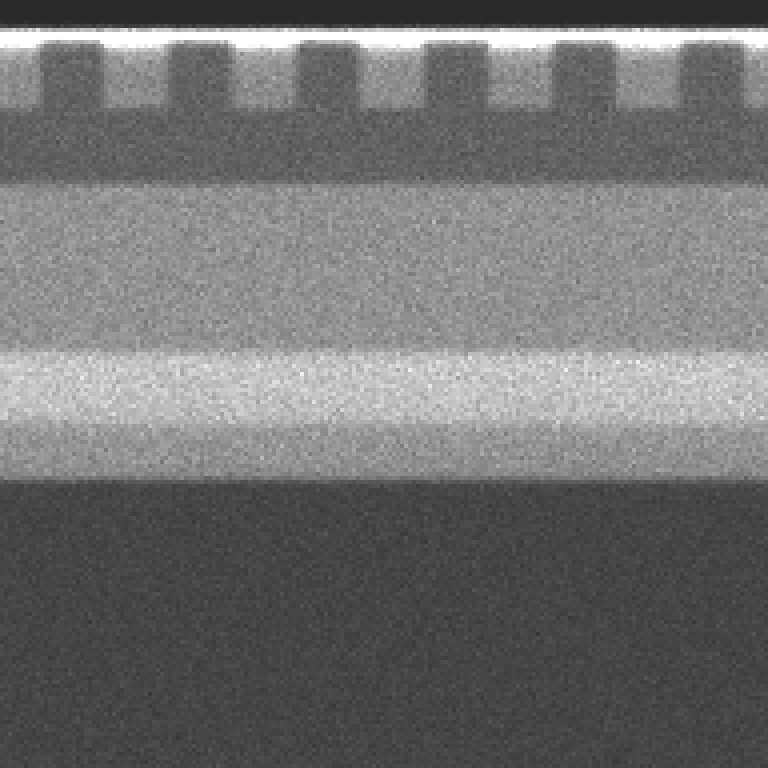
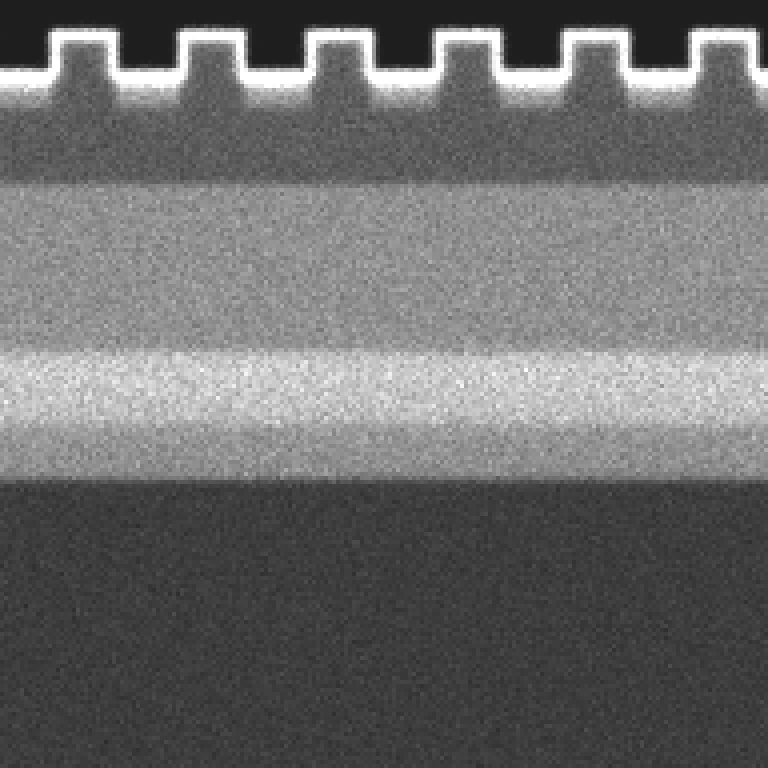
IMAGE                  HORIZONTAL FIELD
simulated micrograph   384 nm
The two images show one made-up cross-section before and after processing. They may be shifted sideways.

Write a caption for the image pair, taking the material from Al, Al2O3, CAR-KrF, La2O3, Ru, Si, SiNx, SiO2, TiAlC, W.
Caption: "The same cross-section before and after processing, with SiO2 removed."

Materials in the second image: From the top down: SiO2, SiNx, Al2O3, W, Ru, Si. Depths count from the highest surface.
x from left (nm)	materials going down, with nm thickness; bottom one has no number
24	empty 20, SiO2 18, SiNx 38, Al2O3 84, W 36, Ru 28, Si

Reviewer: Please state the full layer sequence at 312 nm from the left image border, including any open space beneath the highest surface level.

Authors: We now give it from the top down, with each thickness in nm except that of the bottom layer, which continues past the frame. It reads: SiNx 76, Al2O3 84, W 36, Ru 28, Si